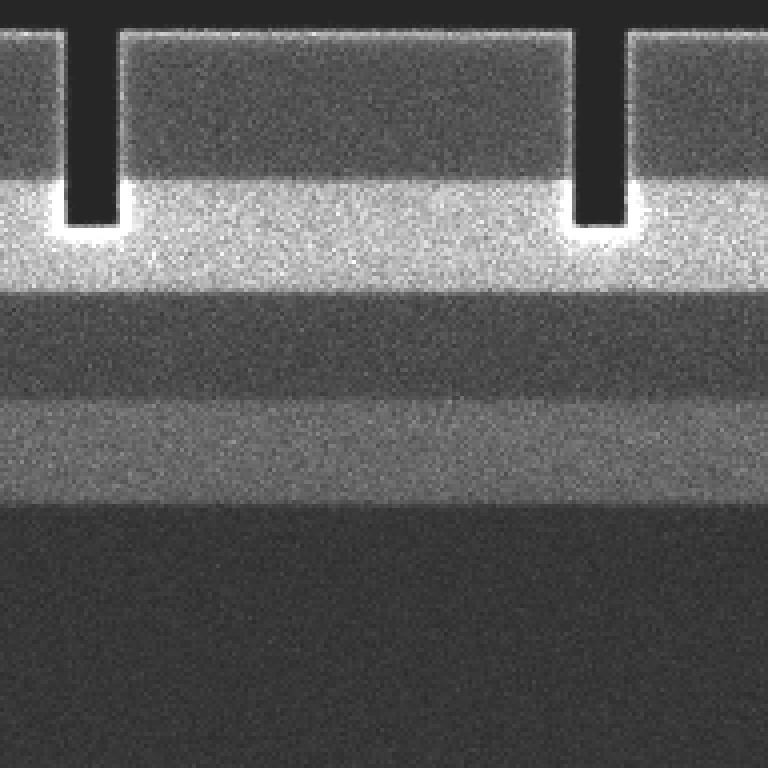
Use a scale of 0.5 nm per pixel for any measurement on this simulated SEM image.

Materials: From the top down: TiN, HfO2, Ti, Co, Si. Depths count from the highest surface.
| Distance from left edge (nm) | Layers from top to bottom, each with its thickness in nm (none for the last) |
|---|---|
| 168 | TiN 74, HfO2 56, Ti 54, Co 52, Si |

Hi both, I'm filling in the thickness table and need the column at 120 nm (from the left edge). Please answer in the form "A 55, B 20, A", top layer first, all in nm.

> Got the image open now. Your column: TiN 74, HfO2 56, Ti 54, Co 52, Si